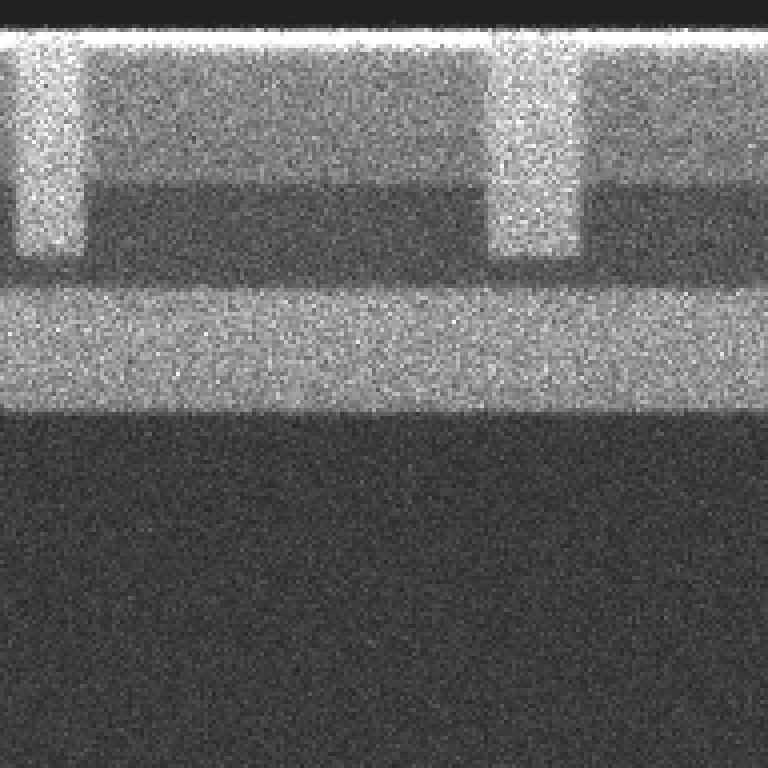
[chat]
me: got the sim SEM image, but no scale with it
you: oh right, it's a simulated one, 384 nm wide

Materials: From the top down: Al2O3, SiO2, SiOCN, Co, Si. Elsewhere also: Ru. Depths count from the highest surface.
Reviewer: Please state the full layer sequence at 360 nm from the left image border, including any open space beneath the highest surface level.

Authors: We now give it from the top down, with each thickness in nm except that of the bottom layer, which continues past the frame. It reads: Al2O3 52, SiO2 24, SiOCN 52, Co 62, Si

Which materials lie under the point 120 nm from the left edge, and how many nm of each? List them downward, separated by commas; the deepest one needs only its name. Al2O3 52, SiO2 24, SiOCN 52, Co 62, Si